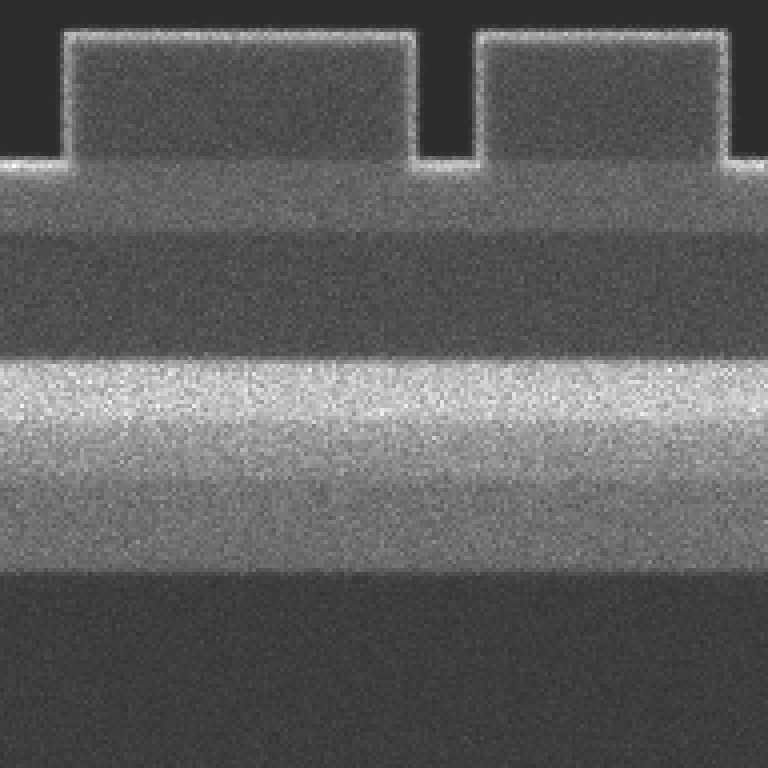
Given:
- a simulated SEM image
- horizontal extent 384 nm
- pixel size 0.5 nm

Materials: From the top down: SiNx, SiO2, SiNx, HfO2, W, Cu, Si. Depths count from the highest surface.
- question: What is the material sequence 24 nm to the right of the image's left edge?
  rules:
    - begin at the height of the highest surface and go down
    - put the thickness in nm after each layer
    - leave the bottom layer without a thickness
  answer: empty 64, SiO2 36, SiNx 64, HfO2 30, W 30, Cu 46, Si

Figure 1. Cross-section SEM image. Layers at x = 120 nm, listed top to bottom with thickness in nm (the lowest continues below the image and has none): SiNx 64, SiO2 36, SiNx 64, HfO2 30, W 30, Cu 46, Si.